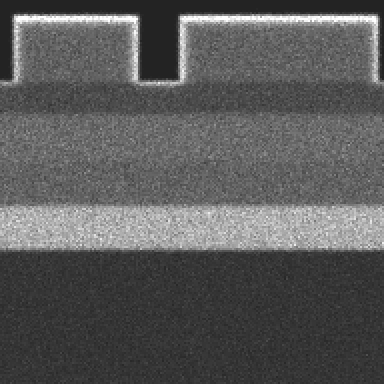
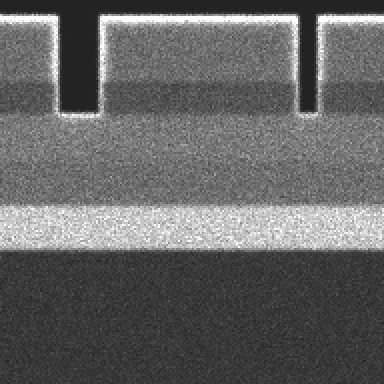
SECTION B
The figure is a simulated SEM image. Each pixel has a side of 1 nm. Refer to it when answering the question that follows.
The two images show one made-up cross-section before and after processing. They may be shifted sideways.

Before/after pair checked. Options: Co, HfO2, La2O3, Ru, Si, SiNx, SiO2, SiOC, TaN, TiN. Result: removed TiN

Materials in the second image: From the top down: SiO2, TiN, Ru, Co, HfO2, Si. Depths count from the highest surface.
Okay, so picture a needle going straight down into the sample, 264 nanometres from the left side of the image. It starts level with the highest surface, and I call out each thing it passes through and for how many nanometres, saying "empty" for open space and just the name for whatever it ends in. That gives SiO2 66, TiN 32, Ru 48, Co 44, HfO2 44, Si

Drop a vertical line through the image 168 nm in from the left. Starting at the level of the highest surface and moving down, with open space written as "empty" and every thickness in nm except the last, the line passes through SiO2 66, TiN 32, Ru 48, Co 44, HfO2 44, Si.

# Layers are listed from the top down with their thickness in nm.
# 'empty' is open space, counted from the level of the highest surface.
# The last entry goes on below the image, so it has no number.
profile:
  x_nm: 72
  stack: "empty 98, Ru 48, Co 44, HfO2 44, Si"